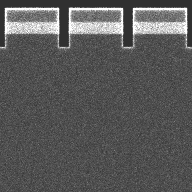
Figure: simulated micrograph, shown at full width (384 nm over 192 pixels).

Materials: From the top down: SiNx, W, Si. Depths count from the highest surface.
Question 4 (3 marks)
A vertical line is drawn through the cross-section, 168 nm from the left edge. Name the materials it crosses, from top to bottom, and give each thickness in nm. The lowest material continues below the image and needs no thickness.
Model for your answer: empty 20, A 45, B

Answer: SiNx 28, W 24, Si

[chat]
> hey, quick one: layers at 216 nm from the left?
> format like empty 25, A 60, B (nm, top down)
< SiNx 28, W 24, Si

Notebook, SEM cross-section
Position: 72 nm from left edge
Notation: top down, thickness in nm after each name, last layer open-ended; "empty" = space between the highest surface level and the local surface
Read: SiNx 28, W 24, Si